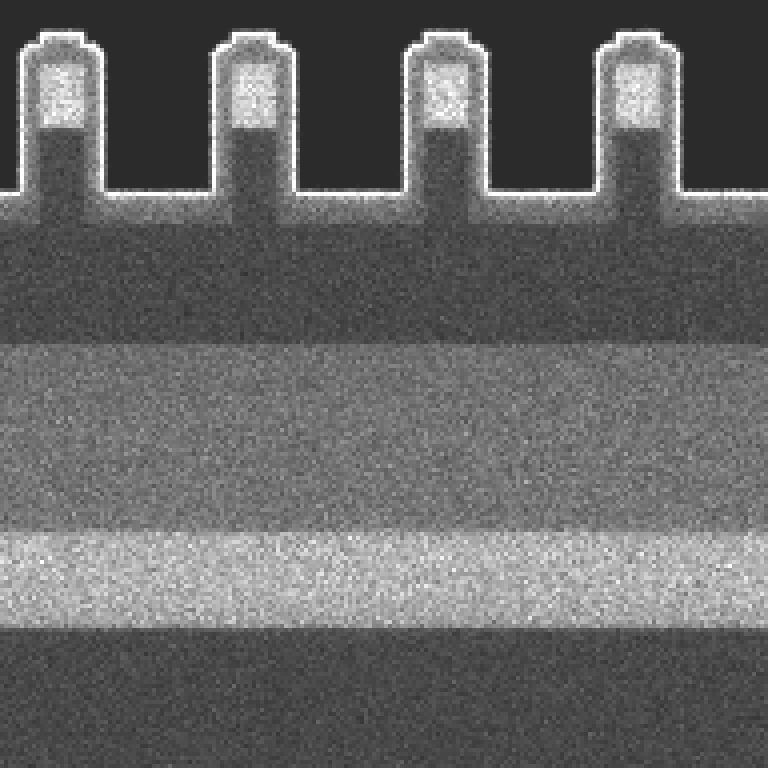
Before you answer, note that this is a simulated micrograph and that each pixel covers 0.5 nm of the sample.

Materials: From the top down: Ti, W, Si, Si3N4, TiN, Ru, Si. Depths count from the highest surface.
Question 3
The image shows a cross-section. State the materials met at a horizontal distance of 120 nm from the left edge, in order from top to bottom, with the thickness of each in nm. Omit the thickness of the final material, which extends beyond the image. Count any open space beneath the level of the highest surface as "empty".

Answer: Ti 16, W 32, Si 108, Si3N4 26, TiN 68, Ru 48, Si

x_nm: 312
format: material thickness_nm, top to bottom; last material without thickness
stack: Ti 16, W 32, Si 108, Si3N4 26, TiN 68, Ru 48, Si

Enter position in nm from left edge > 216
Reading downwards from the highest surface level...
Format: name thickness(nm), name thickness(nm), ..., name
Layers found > Ti 16, W 32, Si 108, Si3N4 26, TiN 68, Ru 48, Si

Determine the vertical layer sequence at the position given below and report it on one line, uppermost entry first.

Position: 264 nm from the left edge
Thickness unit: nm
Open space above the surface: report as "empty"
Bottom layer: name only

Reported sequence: empty 80, Ti 16, Si 60, Si3N4 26, TiN 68, Ru 48, Si